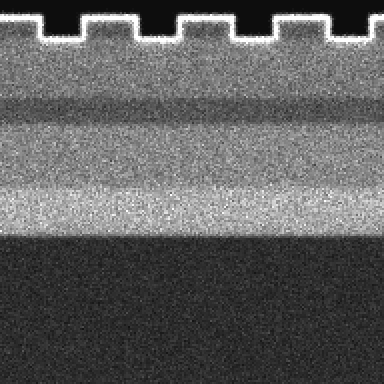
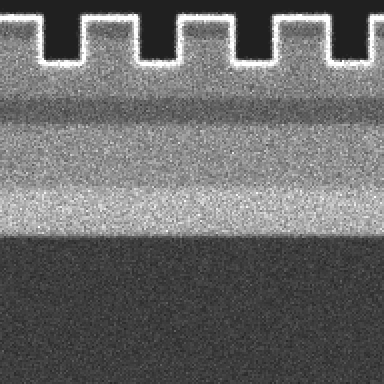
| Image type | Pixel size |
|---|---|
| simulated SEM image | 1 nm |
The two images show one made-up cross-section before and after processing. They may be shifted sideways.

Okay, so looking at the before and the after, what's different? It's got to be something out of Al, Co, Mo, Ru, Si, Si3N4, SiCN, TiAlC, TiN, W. Co, removed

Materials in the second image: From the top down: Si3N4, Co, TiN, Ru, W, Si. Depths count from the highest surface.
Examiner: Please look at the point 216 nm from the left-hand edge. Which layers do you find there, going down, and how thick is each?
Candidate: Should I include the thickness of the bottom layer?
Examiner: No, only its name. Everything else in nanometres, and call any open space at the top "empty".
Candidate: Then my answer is Si3N4 22, Co 60, TiN 26, Ru 64, W 48, Si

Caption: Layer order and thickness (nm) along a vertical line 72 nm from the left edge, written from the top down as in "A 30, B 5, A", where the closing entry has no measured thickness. empty 46, Co 36, TiN 26, Ru 64, W 48, Si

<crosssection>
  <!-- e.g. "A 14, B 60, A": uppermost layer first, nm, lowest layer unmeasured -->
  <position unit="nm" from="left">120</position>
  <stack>Si3N4 22, Co 60, TiN 26, Ru 64, W 48, Si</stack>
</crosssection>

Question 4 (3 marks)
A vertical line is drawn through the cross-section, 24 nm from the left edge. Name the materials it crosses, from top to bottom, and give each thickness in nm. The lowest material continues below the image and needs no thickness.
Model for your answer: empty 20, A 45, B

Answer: Si3N4 22, Co 60, TiN 26, Ru 64, W 48, Si